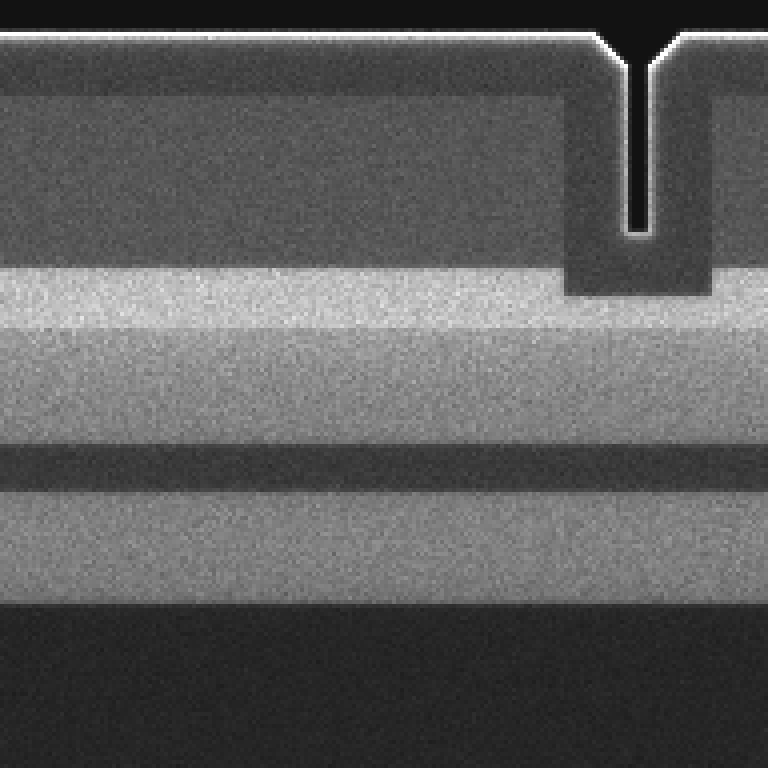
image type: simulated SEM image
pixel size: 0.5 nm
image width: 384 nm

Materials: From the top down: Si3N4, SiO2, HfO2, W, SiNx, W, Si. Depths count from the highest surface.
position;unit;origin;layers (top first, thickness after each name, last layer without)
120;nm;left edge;Si3N4 32, SiO2 86, HfO2 30, W 58, SiNx 24, W 56, Si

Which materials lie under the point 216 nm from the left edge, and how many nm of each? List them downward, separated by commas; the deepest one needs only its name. Si3N4 32, SiO2 86, HfO2 30, W 58, SiNx 24, W 56, Si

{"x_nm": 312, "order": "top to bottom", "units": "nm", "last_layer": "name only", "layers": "empty 16, Si3N4 116, HfO2 16, W 58, SiNx 24, W 56, Si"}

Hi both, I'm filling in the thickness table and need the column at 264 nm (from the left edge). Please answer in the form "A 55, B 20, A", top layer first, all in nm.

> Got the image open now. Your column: Si3N4 32, SiO2 86, HfO2 30, W 58, SiNx 24, W 56, Si